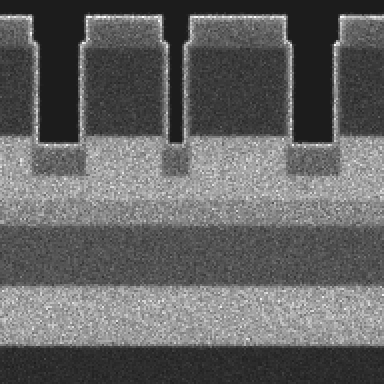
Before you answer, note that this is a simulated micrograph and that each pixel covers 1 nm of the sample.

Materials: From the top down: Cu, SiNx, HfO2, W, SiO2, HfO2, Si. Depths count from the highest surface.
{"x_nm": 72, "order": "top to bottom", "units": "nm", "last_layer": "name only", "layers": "empty 128, Cu 32, HfO2 24, W 26, SiO2 60, HfO2 60, Si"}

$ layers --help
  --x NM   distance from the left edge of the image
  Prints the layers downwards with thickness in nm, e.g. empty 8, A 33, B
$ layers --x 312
empty 128, Cu 32, HfO2 24, W 26, SiO2 60, HfO2 60, Si